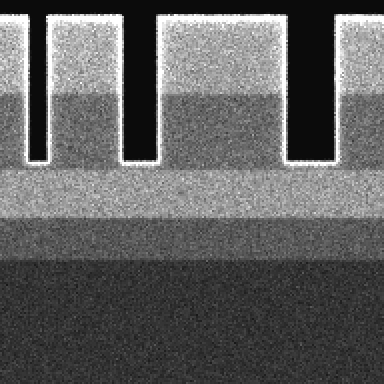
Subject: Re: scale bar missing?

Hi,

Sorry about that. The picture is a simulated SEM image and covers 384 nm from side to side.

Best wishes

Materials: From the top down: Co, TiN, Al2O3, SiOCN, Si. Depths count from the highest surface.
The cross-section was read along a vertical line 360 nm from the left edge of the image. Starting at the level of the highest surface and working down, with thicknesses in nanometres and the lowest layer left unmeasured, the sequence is Co 78, TiN 76, Al2O3 48, SiOCN 42, Si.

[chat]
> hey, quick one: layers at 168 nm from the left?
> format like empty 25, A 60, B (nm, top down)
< Co 78, TiN 76, Al2O3 48, SiOCN 42, Si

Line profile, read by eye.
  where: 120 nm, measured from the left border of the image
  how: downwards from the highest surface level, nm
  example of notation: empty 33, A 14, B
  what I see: Co 78, TiN 76, Al2O3 48, SiOCN 42, Si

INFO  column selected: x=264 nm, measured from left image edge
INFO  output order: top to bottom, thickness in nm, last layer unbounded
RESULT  Co 78, TiN 76, Al2O3 48, SiOCN 42, Si